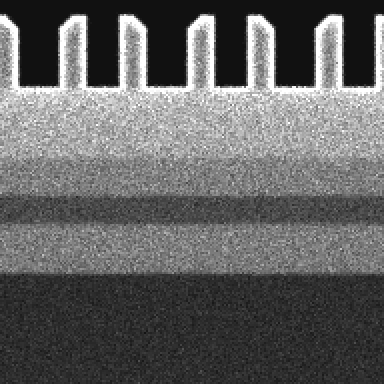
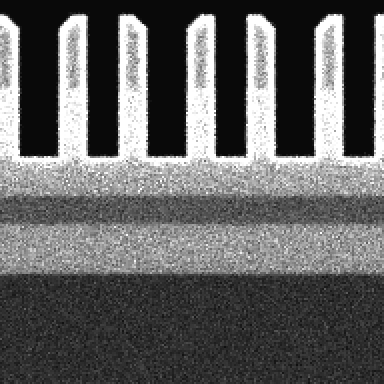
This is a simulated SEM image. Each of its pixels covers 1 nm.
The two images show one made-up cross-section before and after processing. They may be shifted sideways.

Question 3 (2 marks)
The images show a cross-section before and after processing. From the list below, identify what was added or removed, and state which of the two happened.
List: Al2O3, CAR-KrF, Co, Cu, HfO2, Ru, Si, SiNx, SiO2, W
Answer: W was removed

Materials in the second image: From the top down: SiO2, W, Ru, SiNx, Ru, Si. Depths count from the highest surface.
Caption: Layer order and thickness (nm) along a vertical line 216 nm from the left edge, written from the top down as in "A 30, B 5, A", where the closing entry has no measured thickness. empty 142, Ru 38, SiNx 28, Ru 50, Si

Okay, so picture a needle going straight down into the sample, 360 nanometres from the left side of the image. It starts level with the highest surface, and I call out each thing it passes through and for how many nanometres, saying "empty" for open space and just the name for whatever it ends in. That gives empty 142, Ru 38, SiNx 28, Ru 50, Si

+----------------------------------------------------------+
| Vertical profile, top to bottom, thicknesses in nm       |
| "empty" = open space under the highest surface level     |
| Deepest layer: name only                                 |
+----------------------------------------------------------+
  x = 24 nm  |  empty 142, Ru 38, SiNx 28, Ru 50, Si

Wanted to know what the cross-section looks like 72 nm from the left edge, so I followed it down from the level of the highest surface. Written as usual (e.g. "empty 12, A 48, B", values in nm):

SiO2 72, W 70, Ru 38, SiNx 28, Ru 50, Si